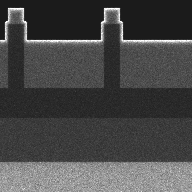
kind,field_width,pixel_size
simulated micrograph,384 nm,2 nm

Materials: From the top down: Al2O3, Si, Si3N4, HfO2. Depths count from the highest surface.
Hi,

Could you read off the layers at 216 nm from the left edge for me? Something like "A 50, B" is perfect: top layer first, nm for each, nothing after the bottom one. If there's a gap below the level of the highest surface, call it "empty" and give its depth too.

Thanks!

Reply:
Al2O3 32, Si 188, Si3N4 88, HfO2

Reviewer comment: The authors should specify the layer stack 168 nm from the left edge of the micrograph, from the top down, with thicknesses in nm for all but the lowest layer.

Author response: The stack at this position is empty 64, Al2O3 96, Si 60, Si3N4 88, HfO2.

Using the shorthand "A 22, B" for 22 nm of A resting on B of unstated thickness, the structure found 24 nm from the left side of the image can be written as Al2O3 32, Si 188, Si3N4 88, HfO2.